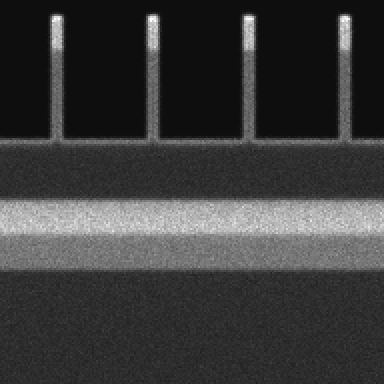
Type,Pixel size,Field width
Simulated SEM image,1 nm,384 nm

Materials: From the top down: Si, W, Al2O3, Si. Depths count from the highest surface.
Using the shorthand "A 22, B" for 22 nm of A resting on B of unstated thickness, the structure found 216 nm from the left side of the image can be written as empty 124, Si 60, W 34, Al2O3 36, Si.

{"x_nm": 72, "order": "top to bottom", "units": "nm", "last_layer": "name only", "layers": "empty 124, Si 60, W 34, Al2O3 36, Si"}